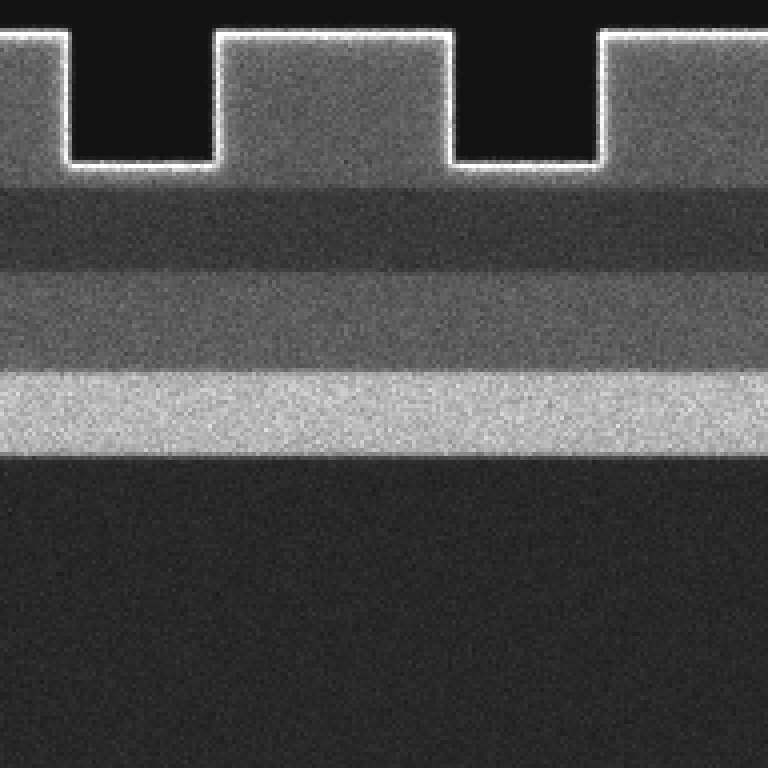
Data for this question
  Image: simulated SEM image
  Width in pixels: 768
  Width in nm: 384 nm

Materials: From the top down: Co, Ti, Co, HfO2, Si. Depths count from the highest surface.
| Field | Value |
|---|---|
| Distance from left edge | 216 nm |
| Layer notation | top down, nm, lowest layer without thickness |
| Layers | Co 78, Ti 42, Co 50, HfO2 42, Si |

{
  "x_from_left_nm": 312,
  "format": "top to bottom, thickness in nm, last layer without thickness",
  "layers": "Co 78, Ti 42, Co 50, HfO2 42, Si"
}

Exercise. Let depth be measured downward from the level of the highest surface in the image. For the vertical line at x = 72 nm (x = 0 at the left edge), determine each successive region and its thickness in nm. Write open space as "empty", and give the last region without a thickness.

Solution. empty 66, Co 12, Ti 42, Co 50, HfO2 42, Si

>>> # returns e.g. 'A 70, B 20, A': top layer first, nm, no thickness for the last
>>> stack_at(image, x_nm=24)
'Co 78, Ti 42, Co 50, HfO2 42, Si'